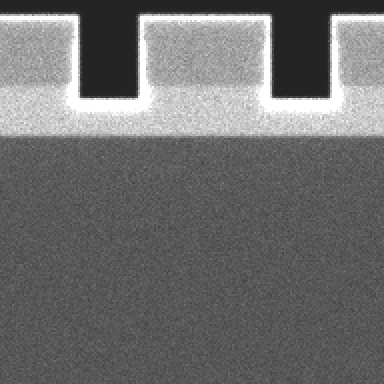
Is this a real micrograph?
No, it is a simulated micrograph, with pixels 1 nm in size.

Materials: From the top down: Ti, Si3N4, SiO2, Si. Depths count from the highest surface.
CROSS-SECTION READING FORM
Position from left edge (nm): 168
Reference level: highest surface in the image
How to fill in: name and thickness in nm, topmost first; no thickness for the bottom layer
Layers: Ti 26, Si3N4 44, SiO2 50, Si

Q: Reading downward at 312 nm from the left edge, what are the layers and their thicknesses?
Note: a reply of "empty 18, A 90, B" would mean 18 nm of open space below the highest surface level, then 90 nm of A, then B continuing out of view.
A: empty 84, SiO2 36, Si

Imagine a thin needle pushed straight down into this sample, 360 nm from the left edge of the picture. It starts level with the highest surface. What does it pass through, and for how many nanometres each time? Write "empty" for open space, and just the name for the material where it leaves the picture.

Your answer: Ti 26, Si3N4 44, SiO2 50, Si